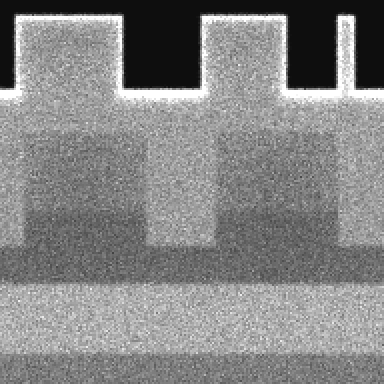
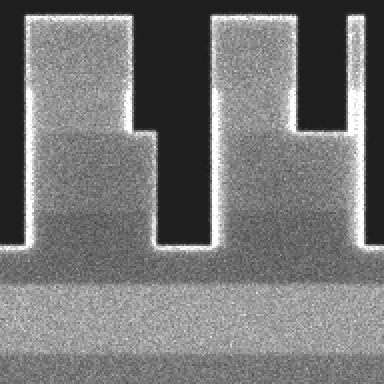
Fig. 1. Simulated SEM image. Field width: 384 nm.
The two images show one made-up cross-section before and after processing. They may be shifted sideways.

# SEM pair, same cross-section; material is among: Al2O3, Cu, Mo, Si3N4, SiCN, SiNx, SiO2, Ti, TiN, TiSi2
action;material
removed;SiO2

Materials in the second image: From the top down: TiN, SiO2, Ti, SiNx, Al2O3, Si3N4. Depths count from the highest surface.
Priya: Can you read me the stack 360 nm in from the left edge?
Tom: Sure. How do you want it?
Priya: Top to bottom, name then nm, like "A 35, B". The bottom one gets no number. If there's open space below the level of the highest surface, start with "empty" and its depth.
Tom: TiN 74, SiO2 156, SiNx 38, Al2O3 70, Si3N4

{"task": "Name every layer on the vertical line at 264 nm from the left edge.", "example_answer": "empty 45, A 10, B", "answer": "TiN 74, SiO2 42, Ti 80, SiNx 72, Al2O3 70, Si3N4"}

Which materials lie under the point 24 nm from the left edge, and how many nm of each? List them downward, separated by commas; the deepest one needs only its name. empty 230, SiNx 38, Al2O3 70, Si3N4